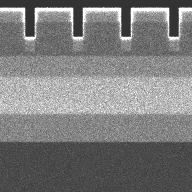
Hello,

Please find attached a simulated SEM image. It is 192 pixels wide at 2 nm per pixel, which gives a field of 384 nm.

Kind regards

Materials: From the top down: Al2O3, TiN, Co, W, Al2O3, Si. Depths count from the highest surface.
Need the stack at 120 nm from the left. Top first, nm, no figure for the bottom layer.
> Al2O3 28, TiN 68, Co 42, W 74, Al2O3 56, Si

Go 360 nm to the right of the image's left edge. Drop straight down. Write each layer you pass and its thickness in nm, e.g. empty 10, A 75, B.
Al2O3 28, TiN 68, Co 42, W 74, Al2O3 56, Si